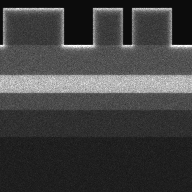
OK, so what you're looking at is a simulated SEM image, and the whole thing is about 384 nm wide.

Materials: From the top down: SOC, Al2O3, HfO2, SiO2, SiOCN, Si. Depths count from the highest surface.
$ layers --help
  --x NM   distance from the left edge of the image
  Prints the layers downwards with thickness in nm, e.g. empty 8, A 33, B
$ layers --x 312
SOC 74, Al2O3 60, HfO2 36, SiO2 34, SiOCN 54, Si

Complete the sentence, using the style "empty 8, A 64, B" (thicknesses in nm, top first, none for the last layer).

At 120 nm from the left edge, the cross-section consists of SOC 74, Al2O3 60, HfO2 36, SiO2 34, SiOCN 54, Si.